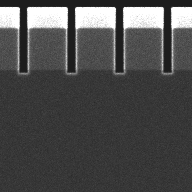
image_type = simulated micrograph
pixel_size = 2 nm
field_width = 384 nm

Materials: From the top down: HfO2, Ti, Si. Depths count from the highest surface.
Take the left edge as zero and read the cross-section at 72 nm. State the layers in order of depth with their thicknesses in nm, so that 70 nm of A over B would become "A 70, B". HfO2 40, Ti 84, Si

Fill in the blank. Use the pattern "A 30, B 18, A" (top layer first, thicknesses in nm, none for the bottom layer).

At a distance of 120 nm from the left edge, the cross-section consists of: HfO2 40, Ti 84, Si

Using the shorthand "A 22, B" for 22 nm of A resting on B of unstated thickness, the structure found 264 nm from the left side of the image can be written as HfO2 40, Ti 84, Si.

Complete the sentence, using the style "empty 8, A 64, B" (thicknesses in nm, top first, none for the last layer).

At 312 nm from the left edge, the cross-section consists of HfO2 40, Ti 84, Si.